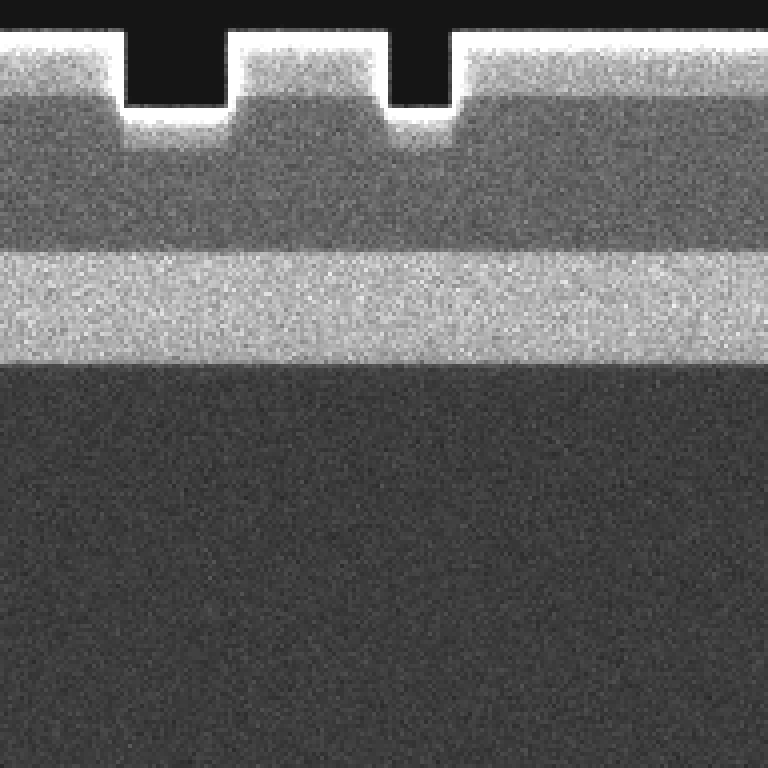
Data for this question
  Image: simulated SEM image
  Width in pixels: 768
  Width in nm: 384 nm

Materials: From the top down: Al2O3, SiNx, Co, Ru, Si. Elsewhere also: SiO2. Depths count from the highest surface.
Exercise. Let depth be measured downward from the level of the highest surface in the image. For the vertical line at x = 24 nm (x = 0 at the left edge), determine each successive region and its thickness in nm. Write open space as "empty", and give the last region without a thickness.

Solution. Al2O3 32, SiNx 78, Co 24, Ru 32, Si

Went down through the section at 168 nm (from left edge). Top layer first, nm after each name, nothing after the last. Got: Al2O3 32, SiNx 78, Co 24, Ru 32, Si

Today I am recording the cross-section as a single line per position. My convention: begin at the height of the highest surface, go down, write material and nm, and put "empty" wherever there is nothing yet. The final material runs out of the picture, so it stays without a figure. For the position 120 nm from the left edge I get Al2O3 32, SiNx 78, Co 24, Ru 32, Si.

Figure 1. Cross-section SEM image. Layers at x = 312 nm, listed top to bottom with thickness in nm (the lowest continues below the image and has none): Al2O3 32, SiNx 78, Co 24, Ru 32, Si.